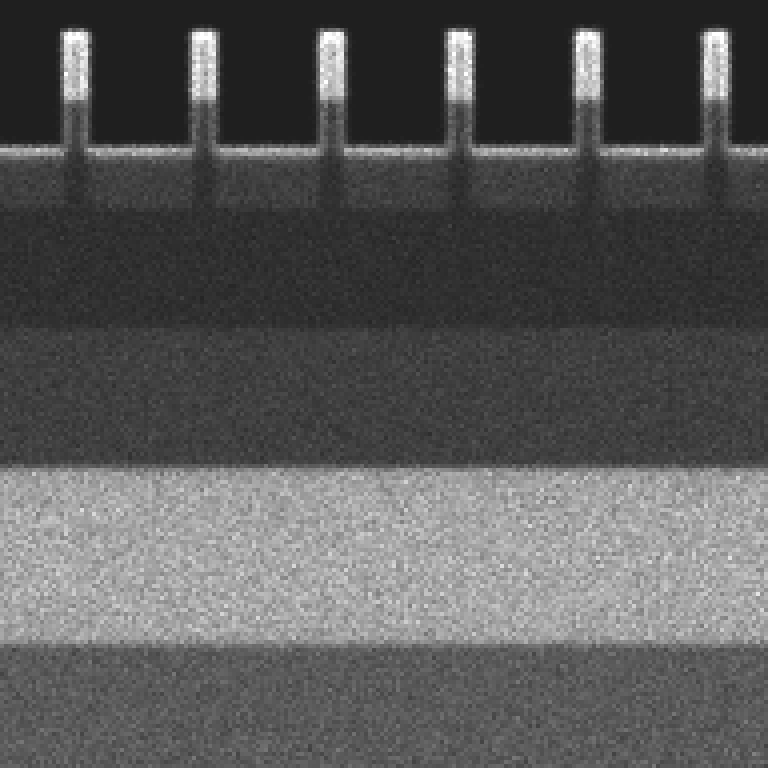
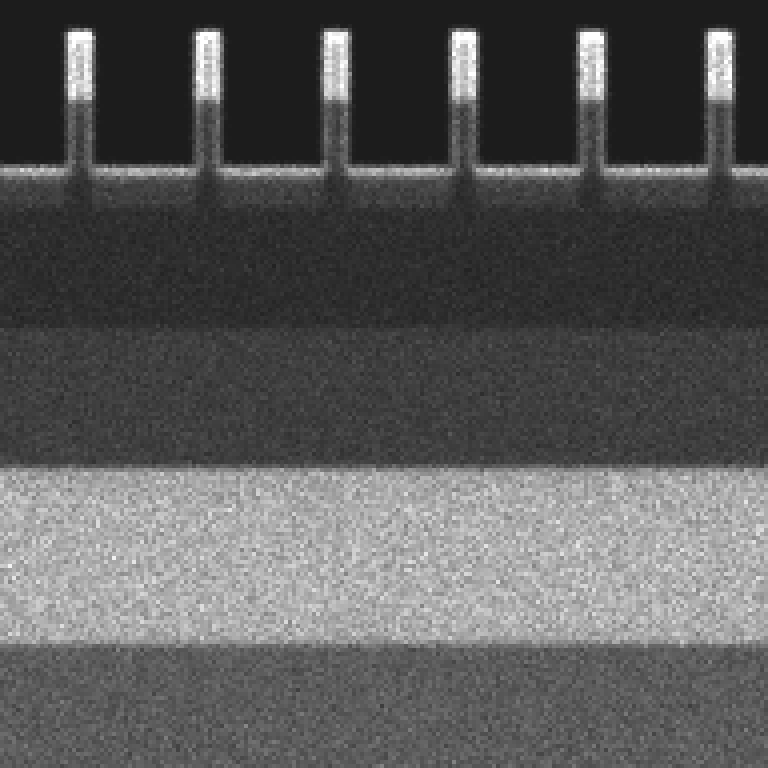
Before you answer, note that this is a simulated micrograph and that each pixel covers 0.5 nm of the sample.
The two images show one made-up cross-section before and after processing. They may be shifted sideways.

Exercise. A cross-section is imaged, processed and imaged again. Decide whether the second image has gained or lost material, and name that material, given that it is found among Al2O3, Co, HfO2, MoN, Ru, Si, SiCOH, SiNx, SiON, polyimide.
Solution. removed: SiNx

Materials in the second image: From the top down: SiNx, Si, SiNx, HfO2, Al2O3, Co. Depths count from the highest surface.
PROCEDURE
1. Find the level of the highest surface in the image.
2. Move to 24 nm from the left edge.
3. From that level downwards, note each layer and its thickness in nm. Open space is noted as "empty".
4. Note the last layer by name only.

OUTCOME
empty 68, SiNx 20, Si 60, SiNx 70, HfO2 88, Al2O3 38, Co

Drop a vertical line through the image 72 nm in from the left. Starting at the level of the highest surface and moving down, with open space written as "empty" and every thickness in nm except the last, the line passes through empty 68, SiNx 20, Si 60, SiNx 70, HfO2 88, Al2O3 38, Co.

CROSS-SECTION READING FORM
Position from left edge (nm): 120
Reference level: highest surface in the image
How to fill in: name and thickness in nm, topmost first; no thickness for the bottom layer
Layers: empty 68, SiNx 20, Si 60, SiNx 70, HfO2 88, Al2O3 38, Co